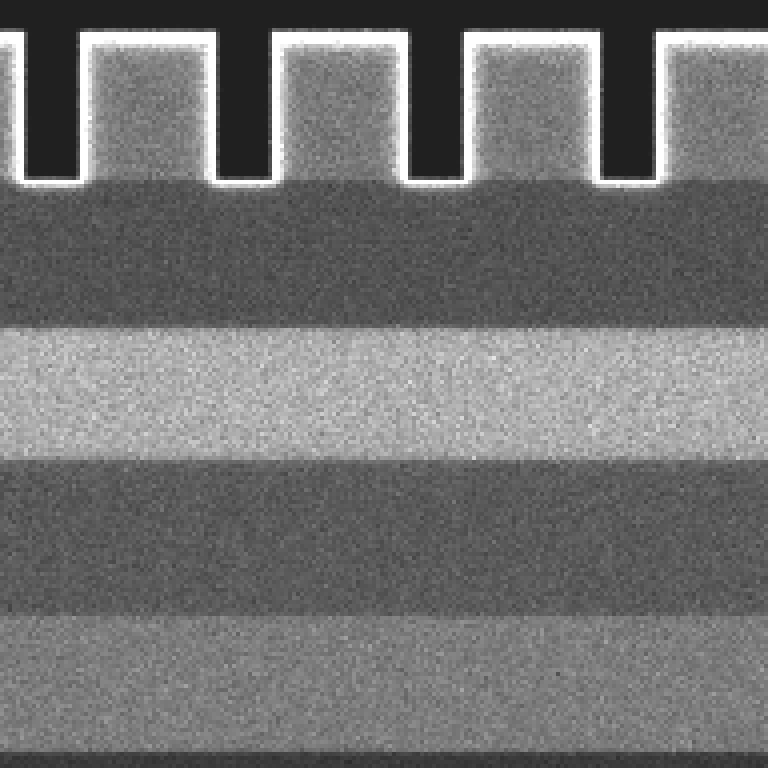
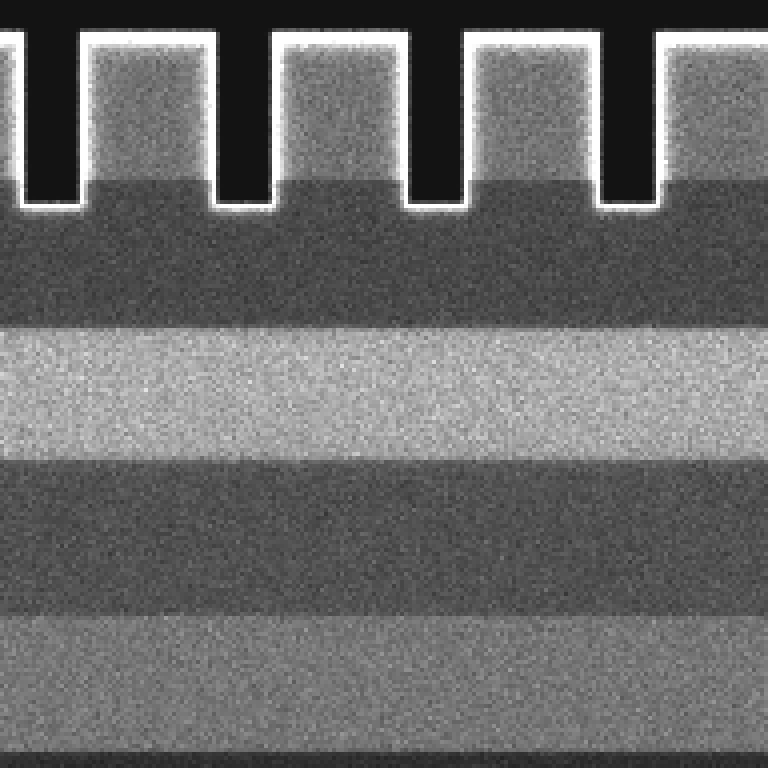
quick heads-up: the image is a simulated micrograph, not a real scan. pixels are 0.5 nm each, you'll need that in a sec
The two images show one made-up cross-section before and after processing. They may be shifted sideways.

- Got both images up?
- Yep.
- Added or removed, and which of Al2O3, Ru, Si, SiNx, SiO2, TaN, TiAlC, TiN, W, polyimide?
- removed, SiNx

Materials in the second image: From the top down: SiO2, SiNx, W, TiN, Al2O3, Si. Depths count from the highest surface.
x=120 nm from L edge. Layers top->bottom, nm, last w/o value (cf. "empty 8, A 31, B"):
empty 86, SiNx 62, W 66, TiN 78, Al2O3 68, Si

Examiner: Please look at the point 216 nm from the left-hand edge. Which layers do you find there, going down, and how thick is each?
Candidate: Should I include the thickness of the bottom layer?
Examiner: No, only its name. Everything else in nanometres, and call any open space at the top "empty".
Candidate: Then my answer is empty 86, SiNx 62, W 66, TiN 78, Al2O3 68, Si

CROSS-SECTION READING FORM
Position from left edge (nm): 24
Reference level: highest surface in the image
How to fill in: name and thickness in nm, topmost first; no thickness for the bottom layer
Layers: empty 86, SiNx 62, W 66, TiN 78, Al2O3 68, Si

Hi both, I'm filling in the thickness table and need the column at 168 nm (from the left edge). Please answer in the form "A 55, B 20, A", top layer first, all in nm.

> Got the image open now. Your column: SiO2 74, SiNx 74, W 66, TiN 78, Al2O3 68, Si